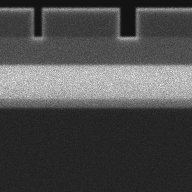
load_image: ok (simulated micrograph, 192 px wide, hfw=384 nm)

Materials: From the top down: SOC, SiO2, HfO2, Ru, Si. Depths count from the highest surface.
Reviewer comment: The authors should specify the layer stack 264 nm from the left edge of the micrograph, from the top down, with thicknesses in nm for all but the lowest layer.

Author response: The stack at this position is empty 58, SiO2 56, HfO2 68, Ru 18, Si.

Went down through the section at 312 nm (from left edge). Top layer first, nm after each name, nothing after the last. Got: SOC 58, SiO2 56, HfO2 68, Ru 18, Si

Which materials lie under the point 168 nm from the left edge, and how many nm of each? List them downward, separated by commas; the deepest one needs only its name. SOC 58, SiO2 56, HfO2 68, Ru 18, Si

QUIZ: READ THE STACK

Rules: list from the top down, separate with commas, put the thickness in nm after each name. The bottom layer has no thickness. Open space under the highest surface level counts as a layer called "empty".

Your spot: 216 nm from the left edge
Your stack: SOC 58, SiO2 56, HfO2 68, Ru 18, Si